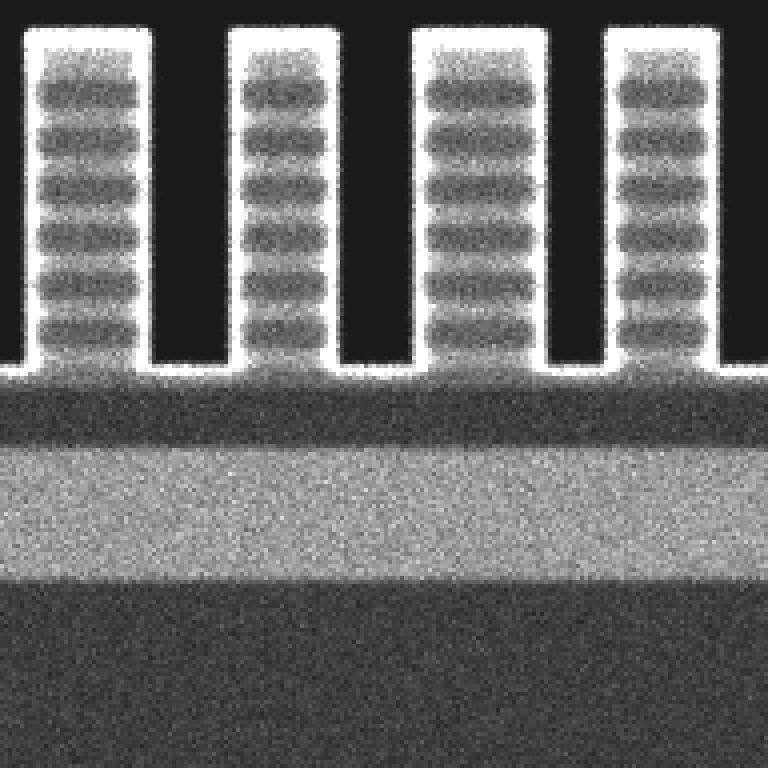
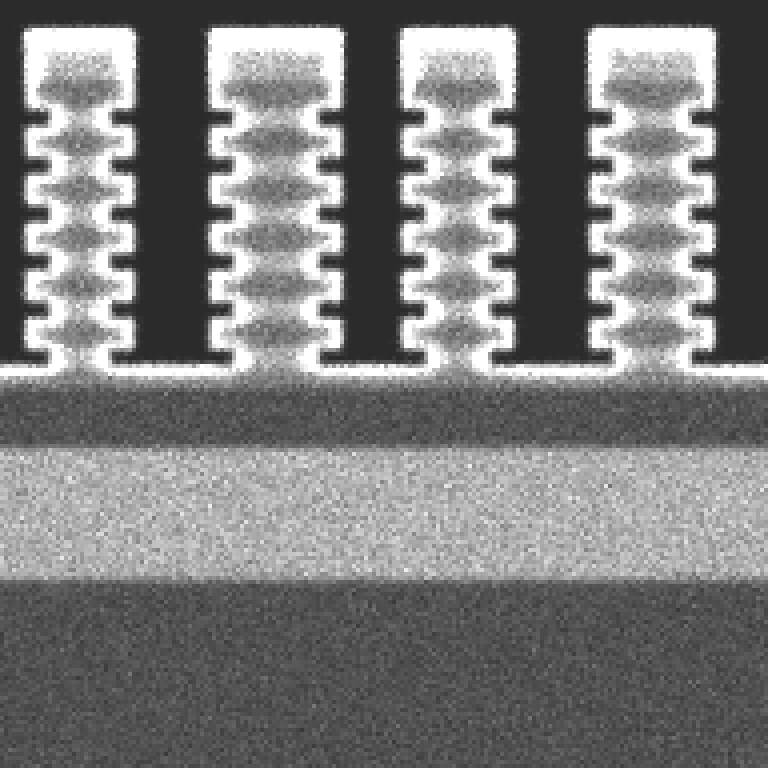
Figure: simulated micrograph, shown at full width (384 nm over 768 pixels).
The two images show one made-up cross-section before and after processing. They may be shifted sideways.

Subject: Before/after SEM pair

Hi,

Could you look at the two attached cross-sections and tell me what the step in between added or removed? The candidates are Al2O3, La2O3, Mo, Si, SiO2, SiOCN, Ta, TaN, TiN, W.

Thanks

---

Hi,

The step removed SiO2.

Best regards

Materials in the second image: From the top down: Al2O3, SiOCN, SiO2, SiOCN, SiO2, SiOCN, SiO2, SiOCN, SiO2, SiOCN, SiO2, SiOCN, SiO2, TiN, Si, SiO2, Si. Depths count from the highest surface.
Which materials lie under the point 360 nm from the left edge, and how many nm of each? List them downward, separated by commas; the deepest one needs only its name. empty 168, TiN 10, Si 30, SiO2 66, Si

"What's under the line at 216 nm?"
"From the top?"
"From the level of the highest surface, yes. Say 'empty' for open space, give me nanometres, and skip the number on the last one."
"Al2O3 24, SiOCN 14, SiO2 10, SiOCN 14, SiO2 10, SiOCN 14, SiO2 10, SiOCN 14, SiO2 10, SiOCN 14, SiO2 10, SiOCN 14, SiO2 10, TiN 10, Si 30, SiO2 66, Si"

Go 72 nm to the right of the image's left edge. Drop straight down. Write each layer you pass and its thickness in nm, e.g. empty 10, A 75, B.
empty 168, TiN 10, Si 30, SiO2 66, Si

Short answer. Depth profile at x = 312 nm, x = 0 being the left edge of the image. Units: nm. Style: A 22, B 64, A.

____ Al2O3 24, SiOCN 14, SiO2 10, SiOCN 14, SiO2 10, SiOCN 14, SiO2 10, SiOCN 14, SiO2 10, SiOCN 14, SiO2 10, SiOCN 14, SiO2 10, TiN 10, Si 30, SiO2 66, Si